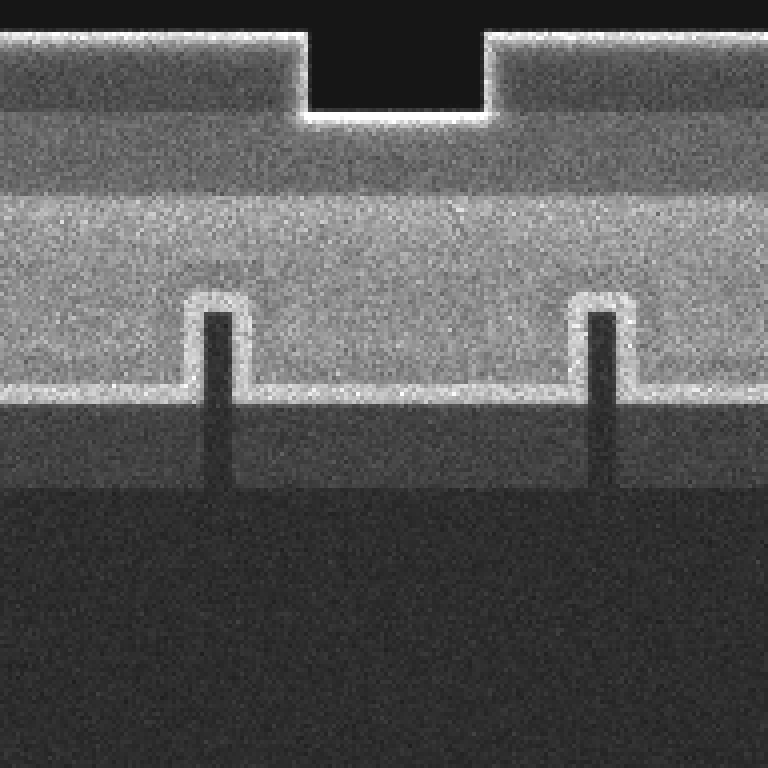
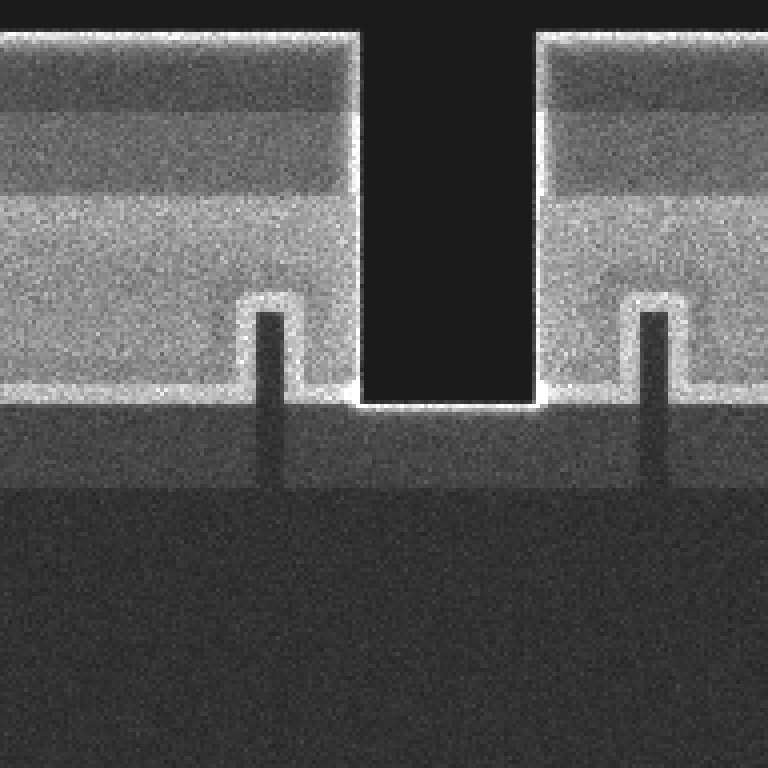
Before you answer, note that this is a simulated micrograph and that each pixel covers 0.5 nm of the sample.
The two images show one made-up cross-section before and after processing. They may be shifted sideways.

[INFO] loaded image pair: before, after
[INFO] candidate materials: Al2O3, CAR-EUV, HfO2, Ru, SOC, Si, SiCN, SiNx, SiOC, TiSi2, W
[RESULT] removed Al2O3 and HfO2 and Ru and W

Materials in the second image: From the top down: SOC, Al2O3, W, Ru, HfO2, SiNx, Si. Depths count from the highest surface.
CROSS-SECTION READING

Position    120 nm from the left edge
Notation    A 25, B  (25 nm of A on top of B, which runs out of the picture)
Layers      SOC 40, Al2O3 42, W 34, Ru 16, HfO2 54, SiNx 42, Si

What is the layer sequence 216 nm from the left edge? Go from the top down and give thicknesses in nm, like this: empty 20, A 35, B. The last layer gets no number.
empty 186, SiNx 42, Si